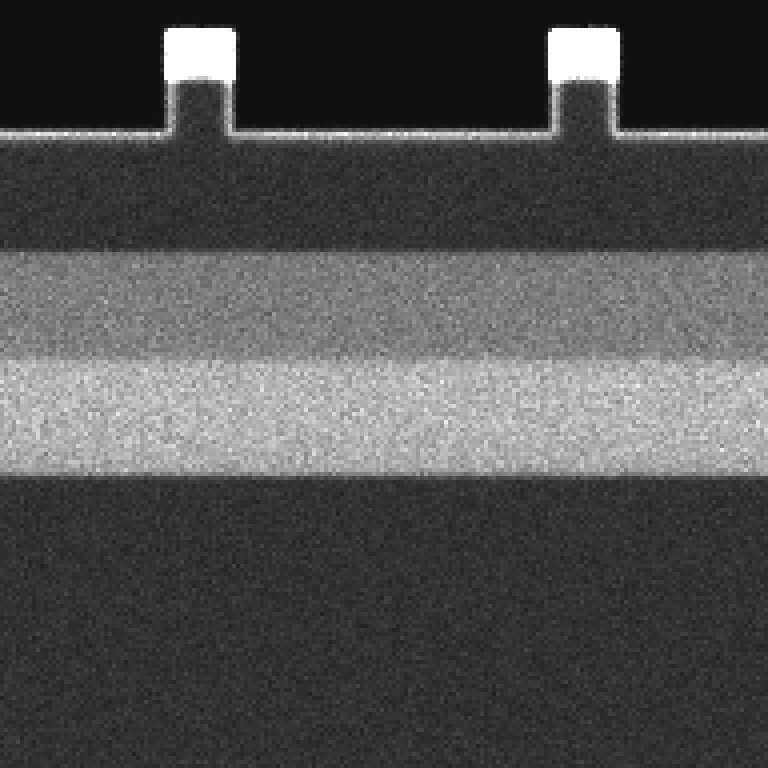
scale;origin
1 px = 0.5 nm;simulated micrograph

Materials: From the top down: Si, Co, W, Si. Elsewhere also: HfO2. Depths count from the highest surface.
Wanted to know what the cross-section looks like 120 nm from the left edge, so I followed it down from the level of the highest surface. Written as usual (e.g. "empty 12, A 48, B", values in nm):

empty 50, Si 60, Co 54, W 58, Si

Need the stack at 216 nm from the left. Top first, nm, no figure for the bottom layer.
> empty 50, Si 60, Co 54, W 58, Si